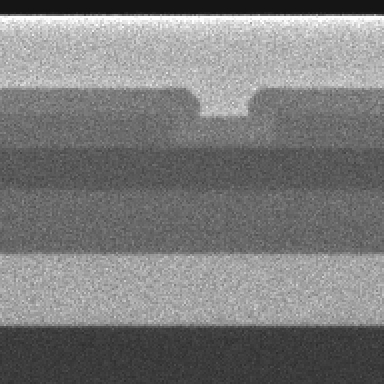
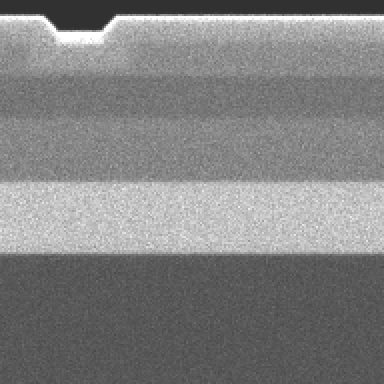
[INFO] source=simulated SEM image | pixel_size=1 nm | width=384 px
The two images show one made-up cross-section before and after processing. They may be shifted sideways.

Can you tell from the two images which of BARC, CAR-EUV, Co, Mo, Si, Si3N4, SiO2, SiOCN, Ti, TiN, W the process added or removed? Yes, it removed W.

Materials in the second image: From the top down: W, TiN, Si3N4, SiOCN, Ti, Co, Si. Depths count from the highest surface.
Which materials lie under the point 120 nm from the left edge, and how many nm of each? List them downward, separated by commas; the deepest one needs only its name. TiN 54, Si3N4 6, SiOCN 42, Ti 64, Co 72, Si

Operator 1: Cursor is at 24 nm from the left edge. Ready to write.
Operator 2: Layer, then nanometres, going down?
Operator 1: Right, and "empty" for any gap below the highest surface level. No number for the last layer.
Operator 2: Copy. TiN 26, Si3N4 34, SiOCN 42, Ti 64, Co 72, Si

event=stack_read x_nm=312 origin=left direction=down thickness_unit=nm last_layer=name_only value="TiN 26, Si3N4 34, SiOCN 42, Ti 64, Co 72, Si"